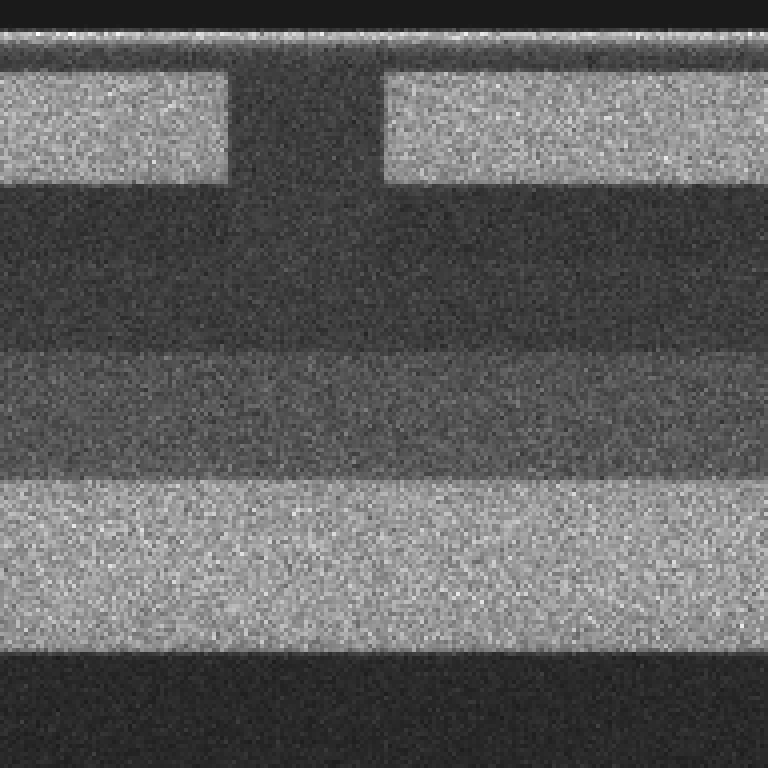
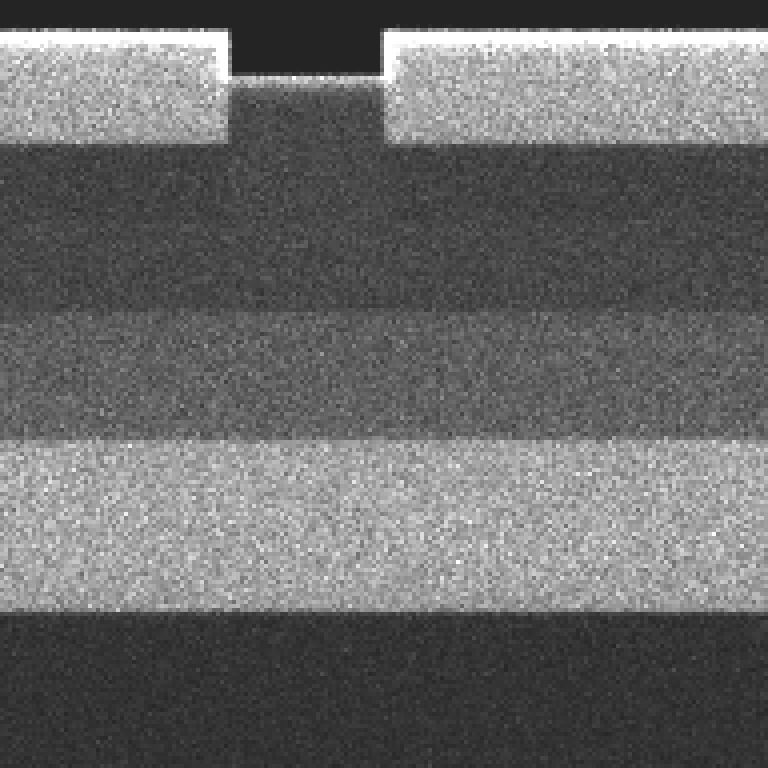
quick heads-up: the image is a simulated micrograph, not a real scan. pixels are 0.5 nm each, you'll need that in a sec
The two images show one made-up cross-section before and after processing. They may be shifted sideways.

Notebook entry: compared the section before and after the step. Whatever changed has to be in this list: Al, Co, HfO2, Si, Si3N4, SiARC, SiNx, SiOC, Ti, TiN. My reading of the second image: SiARC removed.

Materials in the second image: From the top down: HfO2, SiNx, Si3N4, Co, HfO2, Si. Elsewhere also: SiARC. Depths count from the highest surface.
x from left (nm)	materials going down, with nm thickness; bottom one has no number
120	empty 22, SiARC 118, Co 64, HfO2 86, Si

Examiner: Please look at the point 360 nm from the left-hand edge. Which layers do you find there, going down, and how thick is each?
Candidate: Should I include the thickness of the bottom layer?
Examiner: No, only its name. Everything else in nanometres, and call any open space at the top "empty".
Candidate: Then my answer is HfO2 56, SiNx 38, Si3N4 46, Co 64, HfO2 86, Si